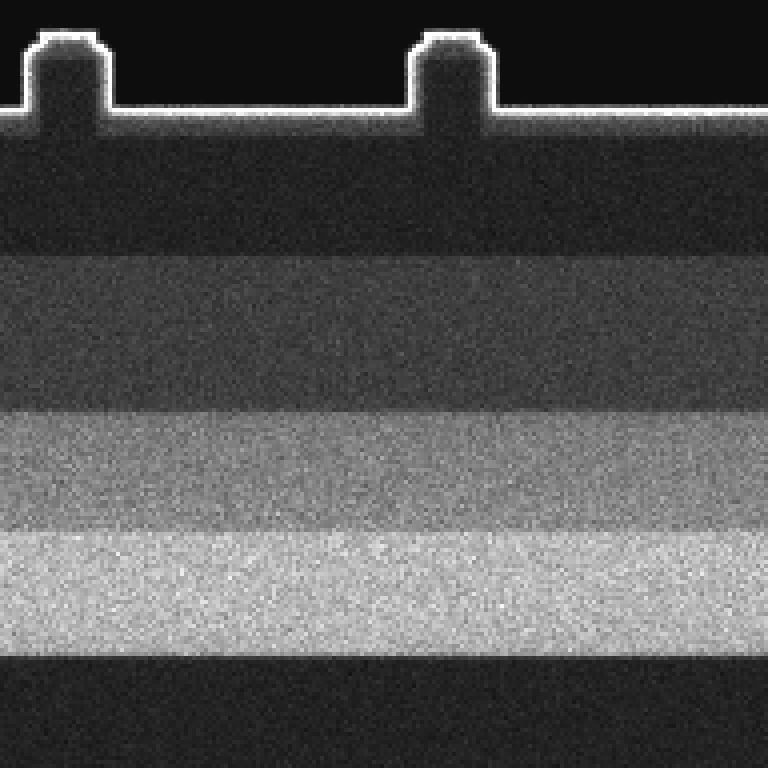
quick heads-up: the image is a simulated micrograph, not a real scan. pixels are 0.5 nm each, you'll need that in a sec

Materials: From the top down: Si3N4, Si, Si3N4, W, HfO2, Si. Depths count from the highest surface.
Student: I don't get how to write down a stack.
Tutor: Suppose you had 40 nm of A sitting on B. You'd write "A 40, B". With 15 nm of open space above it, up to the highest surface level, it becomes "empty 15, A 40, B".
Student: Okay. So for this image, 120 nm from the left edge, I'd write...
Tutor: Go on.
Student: empty 38, Si3N4 14, Si 60, Si3N4 78, W 60, HfO2 62, Si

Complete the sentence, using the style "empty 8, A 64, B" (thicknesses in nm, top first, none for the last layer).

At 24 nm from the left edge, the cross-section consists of Si3N4 14, Si 98, Si3N4 78, W 60, HfO2 62, Si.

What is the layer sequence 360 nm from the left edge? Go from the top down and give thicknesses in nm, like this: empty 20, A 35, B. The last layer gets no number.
empty 38, Si3N4 14, Si 60, Si3N4 78, W 60, HfO2 62, Si